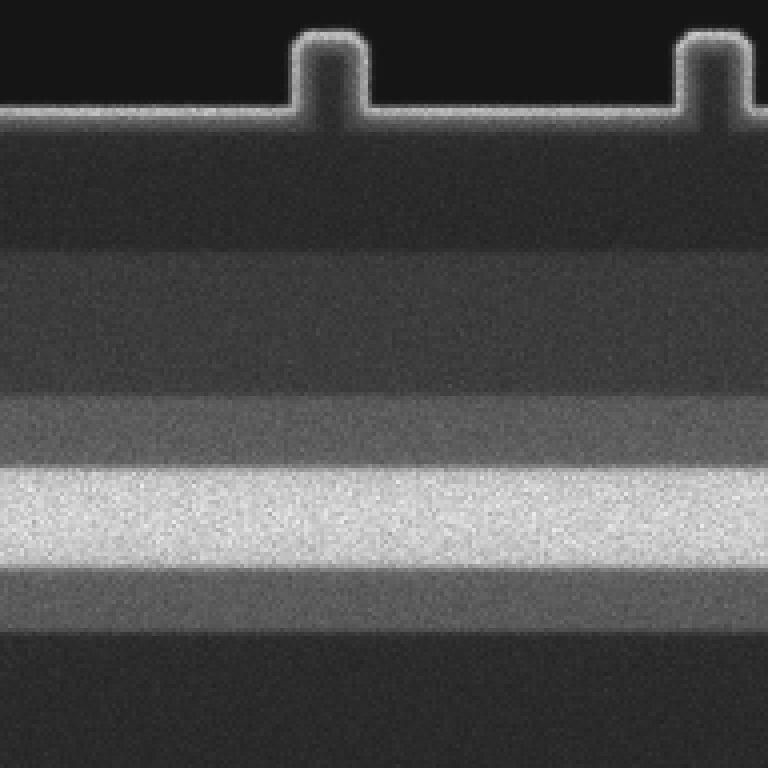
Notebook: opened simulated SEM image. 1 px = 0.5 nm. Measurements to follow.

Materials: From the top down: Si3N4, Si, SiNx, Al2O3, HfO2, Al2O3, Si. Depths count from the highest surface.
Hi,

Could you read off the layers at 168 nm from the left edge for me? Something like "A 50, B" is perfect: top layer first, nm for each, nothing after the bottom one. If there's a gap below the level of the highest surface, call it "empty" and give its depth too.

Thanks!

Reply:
Si3N4 12, Si 98, SiNx 72, Al2O3 36, HfO2 50, Al2O3 32, Si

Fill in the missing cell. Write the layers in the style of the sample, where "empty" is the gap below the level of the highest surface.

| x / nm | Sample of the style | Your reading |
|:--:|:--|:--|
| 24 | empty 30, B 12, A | empty 38, Si3N4 12, Si 60, SiNx 72, Al2O3 36, HfO2 50, Al2O3 32, Si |